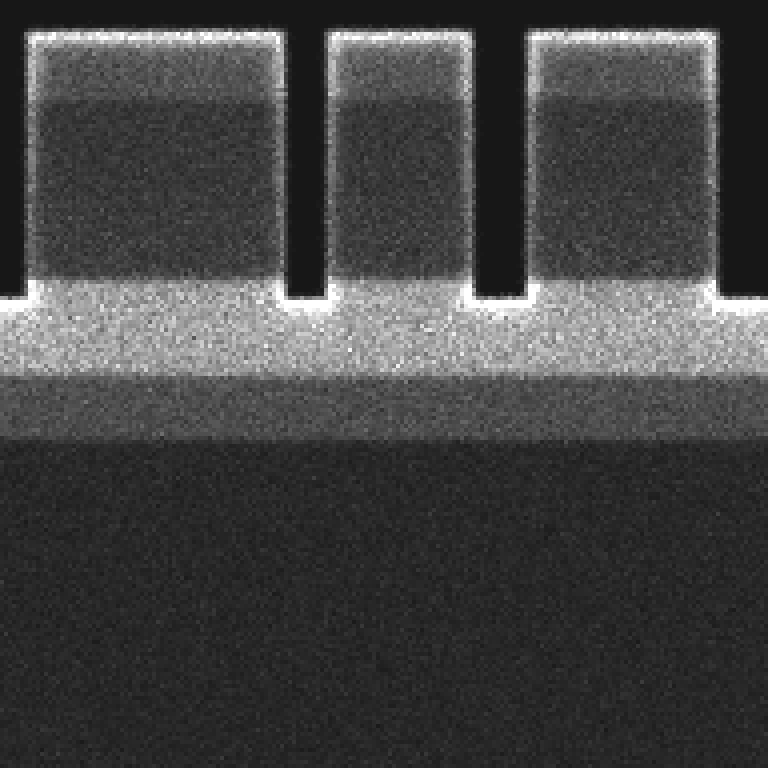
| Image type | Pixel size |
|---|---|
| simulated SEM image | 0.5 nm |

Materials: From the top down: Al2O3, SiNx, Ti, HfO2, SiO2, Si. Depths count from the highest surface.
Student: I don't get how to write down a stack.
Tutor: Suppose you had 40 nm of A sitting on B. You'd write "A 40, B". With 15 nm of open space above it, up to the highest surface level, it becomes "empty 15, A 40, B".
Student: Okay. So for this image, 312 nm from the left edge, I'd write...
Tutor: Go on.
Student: Al2O3 34, SiNx 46, Ti 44, HfO2 48, SiO2 32, Si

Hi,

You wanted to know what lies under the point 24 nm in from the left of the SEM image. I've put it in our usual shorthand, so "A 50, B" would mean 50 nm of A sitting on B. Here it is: Al2O3 34, SiNx 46, Ti 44, HfO2 48, SiO2 32, Si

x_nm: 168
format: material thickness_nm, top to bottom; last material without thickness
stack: Al2O3 34, SiNx 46, Ti 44, HfO2 48, SiO2 32, Si